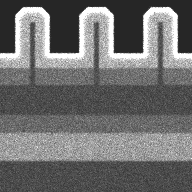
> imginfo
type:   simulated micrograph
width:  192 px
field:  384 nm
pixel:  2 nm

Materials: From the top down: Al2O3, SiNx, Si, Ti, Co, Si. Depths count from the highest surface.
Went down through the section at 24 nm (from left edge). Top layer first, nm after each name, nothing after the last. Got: empty 92, Al2O3 28, SiNx 34, Si 60, Ti 36, Co 56, Si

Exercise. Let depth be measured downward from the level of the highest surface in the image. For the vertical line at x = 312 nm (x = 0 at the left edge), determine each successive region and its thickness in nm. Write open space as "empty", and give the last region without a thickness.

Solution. Al2O3 120, SiNx 34, Si 60, Ti 36, Co 56, Si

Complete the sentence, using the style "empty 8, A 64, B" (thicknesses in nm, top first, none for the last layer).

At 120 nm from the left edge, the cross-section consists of empty 92, Al2O3 28, SiNx 34, Si 60, Ti 36, Co 56, Si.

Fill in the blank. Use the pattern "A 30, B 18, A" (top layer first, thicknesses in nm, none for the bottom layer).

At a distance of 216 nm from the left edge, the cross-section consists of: empty 6, Al2O3 114, SiNx 34, Si 60, Ti 36, Co 56, Si